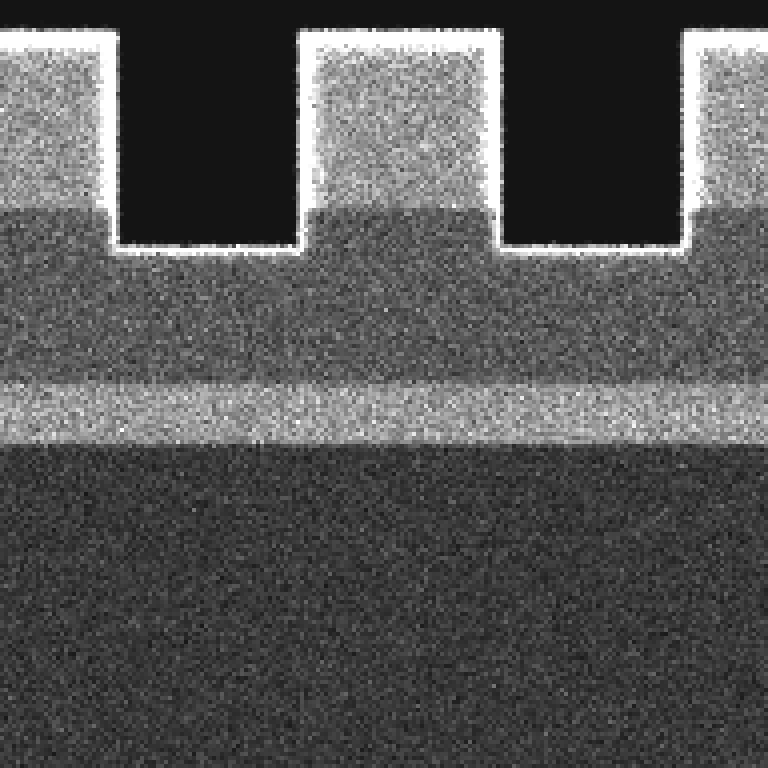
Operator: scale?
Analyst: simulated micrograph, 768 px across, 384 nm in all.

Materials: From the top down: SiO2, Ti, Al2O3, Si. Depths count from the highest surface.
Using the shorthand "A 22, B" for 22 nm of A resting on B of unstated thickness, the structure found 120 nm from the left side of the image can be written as empty 108, Ti 68, Al2O3 30, Si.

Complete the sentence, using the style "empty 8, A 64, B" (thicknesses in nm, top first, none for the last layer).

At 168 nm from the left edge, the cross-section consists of SiO2 88, Ti 88, Al2O3 30, Si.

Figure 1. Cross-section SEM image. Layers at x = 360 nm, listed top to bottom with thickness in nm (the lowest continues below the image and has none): SiO2 88, Ti 88, Al2O3 30, Si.